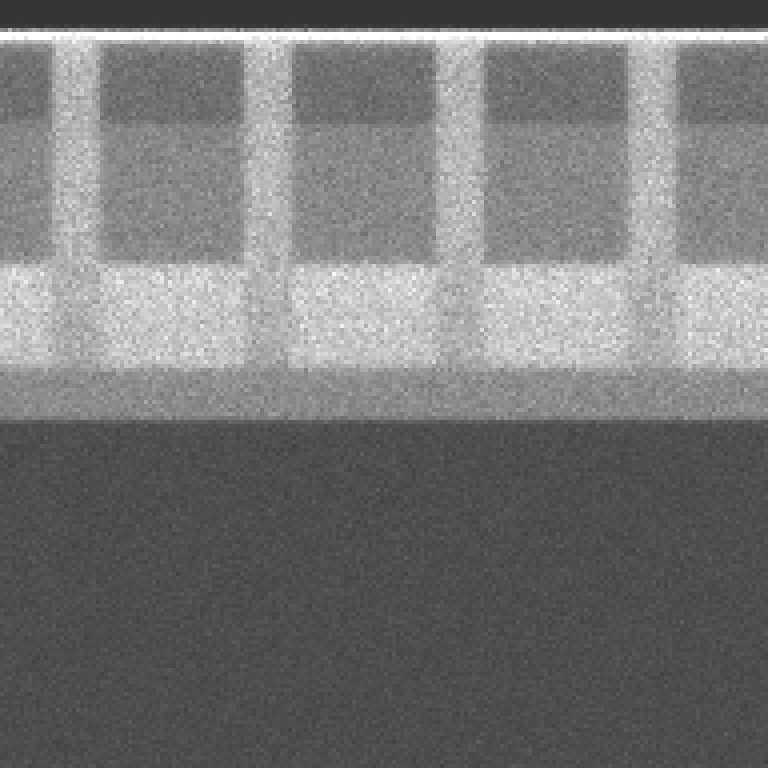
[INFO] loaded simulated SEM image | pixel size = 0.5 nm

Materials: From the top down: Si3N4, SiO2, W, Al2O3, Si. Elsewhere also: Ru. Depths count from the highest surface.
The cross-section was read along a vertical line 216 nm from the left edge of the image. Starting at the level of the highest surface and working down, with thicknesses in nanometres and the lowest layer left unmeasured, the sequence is Si3N4 46, SiO2 70, W 52, Al2O3 26, Si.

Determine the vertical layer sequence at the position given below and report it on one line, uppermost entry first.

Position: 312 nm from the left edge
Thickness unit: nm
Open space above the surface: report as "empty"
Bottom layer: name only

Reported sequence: Si3N4 46, SiO2 70, W 52, Al2O3 26, Si